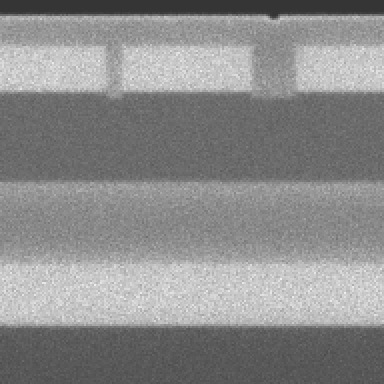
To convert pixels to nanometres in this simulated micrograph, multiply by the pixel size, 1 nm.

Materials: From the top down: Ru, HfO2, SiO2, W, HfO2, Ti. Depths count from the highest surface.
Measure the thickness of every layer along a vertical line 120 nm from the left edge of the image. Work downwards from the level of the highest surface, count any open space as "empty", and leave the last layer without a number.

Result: Ru 82, SiO2 84, W 82, HfO2 62, Ti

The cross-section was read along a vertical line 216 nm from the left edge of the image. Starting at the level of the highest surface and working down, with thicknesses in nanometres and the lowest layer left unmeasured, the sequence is Ru 30, HfO2 46, SiO2 90, W 82, HfO2 62, Ti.